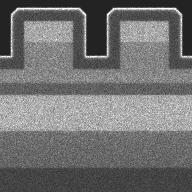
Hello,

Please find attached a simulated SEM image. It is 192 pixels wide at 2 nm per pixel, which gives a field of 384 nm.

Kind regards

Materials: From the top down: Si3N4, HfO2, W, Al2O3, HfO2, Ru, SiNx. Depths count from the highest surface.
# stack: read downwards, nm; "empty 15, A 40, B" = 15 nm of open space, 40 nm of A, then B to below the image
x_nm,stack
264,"Si3N4 26, HfO2 42, W 82, Al2O3 24, HfO2 72, Ru 74, SiNx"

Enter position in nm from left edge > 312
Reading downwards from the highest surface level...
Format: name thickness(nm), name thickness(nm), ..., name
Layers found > Si3N4 26, HfO2 42, W 82, Al2O3 24, HfO2 72, Ru 74, SiNx